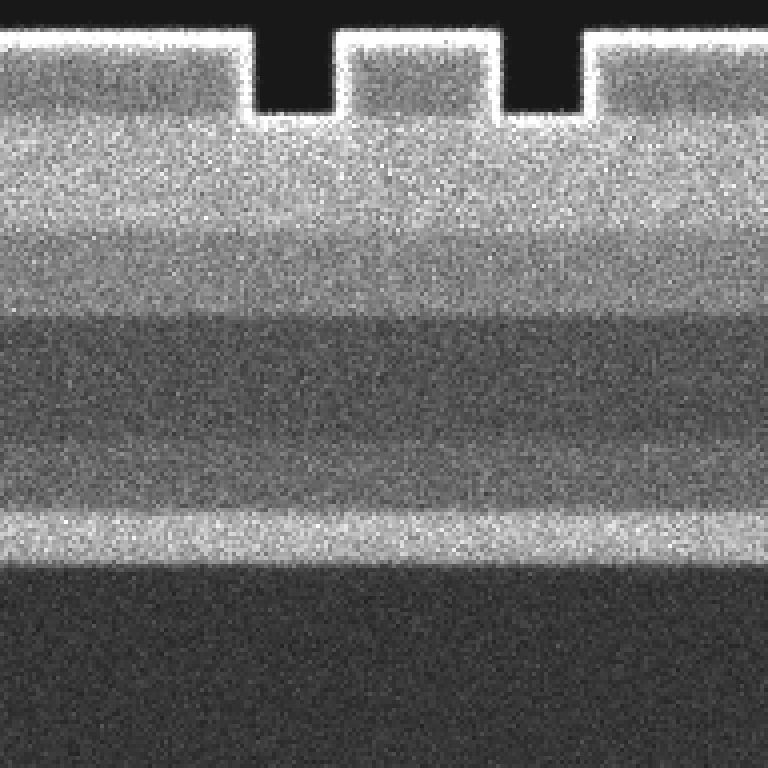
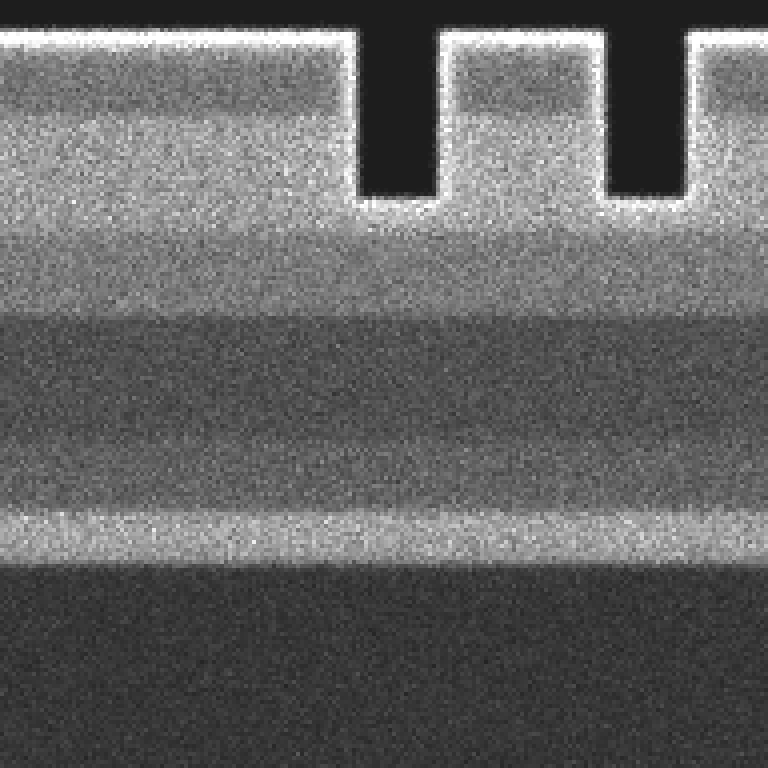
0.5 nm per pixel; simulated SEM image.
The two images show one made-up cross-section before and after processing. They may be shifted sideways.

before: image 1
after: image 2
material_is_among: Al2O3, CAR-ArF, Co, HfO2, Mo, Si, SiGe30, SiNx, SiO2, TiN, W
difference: Co, removed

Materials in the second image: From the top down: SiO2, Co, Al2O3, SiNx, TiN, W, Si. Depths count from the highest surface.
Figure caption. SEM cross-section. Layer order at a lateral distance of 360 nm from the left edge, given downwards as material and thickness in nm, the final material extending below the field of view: SiO2 42, Co 58, Al2O3 42, SiNx 62, TiN 36, W 26, Si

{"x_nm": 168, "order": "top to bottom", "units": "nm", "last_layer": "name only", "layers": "SiO2 42, Co 58, Al2O3 42, SiNx 62, TiN 36, W 26, Si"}